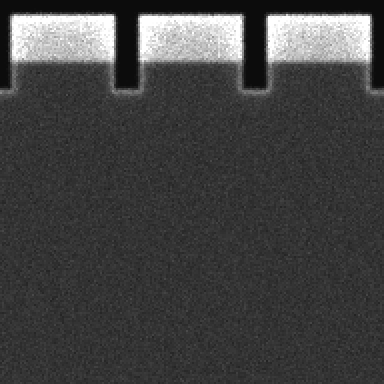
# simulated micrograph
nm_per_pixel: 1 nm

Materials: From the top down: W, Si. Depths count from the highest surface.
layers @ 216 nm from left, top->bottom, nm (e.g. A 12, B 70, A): W 46, Si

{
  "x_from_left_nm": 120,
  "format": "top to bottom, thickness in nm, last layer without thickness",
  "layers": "empty 74, Si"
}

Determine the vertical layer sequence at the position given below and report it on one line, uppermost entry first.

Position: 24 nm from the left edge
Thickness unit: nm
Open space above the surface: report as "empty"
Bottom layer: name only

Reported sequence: W 46, Si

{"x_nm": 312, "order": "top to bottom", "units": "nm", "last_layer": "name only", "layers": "W 46, Si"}